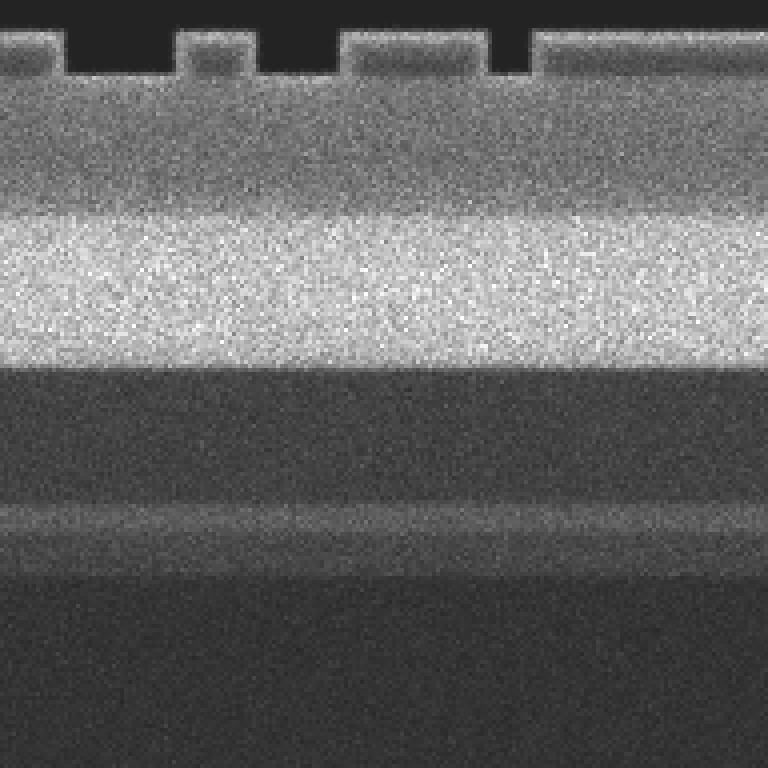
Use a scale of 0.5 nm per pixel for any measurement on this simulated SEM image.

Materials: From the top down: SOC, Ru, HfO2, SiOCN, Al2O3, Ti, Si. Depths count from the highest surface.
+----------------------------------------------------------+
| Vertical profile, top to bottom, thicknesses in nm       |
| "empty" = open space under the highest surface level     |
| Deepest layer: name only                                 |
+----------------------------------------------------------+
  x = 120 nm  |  SOC 22, Ru 70, HfO2 76, SiOCN 68, Al2O3 14, Ti 22, Si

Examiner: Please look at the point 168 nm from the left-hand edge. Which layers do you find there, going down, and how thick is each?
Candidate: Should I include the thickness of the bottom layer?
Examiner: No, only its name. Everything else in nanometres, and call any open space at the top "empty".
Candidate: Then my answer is empty 22, Ru 70, HfO2 76, SiOCN 68, Al2O3 14, Ti 22, Si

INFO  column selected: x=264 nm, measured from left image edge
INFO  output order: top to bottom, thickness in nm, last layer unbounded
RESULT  empty 22, Ru 70, HfO2 76, SiOCN 68, Al2O3 14, Ti 22, Si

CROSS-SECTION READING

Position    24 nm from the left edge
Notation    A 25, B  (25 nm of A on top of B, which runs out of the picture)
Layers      SOC 22, Ru 70, HfO2 76, SiOCN 68, Al2O3 14, Ti 22, Si